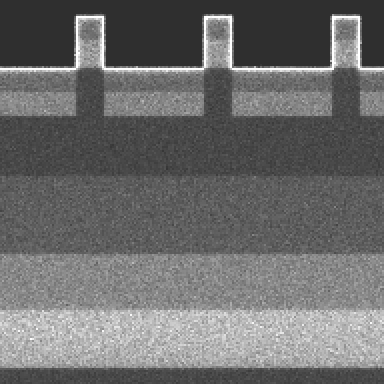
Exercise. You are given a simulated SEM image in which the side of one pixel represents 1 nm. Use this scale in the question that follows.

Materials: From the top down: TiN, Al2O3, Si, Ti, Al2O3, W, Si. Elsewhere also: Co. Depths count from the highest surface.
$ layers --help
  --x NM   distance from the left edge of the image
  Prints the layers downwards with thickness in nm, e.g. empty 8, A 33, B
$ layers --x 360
empty 52, TiN 24, Al2O3 24, Si 60, Ti 78, Al2O3 56, W 58, Si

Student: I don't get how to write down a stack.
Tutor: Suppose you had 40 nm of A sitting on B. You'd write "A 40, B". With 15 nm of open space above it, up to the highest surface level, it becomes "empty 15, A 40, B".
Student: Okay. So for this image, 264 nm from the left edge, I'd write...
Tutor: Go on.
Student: empty 52, TiN 24, Al2O3 24, Si 60, Ti 78, Al2O3 56, W 58, Si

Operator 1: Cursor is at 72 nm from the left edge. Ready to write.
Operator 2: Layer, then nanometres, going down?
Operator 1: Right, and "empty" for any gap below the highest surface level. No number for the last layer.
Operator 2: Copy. empty 52, TiN 24, Al2O3 24, Si 60, Ti 78, Al2O3 56, W 58, Si